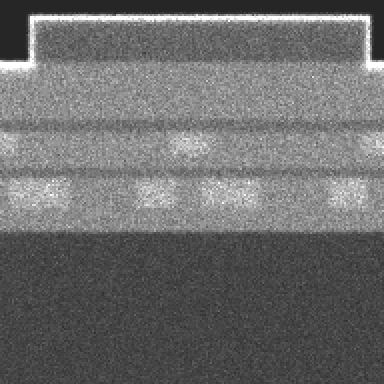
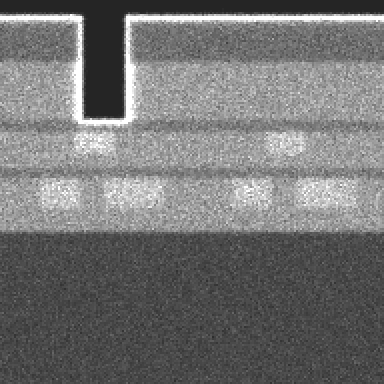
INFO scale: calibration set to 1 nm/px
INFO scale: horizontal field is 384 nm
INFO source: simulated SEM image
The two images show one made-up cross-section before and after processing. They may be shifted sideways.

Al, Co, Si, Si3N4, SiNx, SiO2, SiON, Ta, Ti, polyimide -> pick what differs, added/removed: SiO2 removed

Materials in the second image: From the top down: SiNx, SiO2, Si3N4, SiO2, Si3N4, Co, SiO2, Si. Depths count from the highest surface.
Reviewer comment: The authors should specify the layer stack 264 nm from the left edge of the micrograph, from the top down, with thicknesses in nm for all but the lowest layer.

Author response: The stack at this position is SiNx 46, SiO2 58, Si3N4 12, SiO2 36, Si3N4 10, Co 30, SiO2 24, Si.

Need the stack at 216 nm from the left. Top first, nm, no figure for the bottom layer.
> SiNx 46, SiO2 58, Si3N4 12, SiO2 36, Si3N4 10, SiO2 54, Si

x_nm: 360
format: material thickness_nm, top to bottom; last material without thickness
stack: SiNx 46, SiO2 58, Si3N4 12, SiO2 36, Si3N4 10, SiO2 54, Si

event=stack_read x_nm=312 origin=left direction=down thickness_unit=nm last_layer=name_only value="SiNx 46, SiO2 58, Si3N4 12, SiO2 36, Si3N4 10, Co 30, SiO2 24, Si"